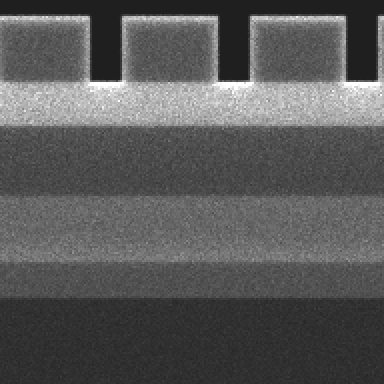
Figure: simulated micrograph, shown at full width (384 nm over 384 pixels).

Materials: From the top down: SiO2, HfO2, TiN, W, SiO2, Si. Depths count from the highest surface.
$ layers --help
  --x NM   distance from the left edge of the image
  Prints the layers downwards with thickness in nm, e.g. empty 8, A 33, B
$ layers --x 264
SiO2 66, HfO2 44, TiN 70, W 66, SiO2 36, Si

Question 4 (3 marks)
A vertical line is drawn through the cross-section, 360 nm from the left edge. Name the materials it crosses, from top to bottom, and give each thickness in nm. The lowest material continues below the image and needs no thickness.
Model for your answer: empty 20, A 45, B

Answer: empty 66, HfO2 44, TiN 70, W 66, SiO2 36, Si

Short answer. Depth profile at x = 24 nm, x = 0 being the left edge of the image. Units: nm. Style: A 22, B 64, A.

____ SiO2 66, HfO2 44, TiN 70, W 66, SiO2 36, Si